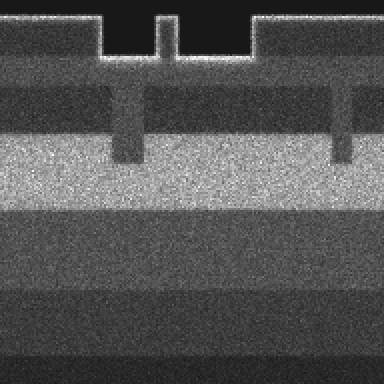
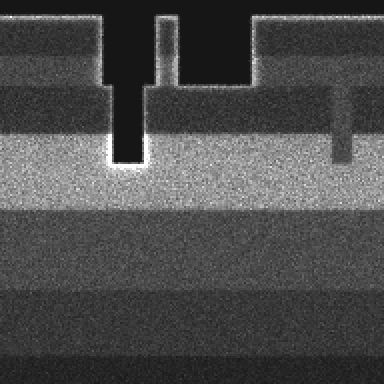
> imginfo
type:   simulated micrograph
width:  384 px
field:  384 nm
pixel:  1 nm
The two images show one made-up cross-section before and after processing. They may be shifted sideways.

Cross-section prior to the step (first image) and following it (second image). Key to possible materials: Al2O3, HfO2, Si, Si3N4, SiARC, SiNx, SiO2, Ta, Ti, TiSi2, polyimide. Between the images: SiO2 was removed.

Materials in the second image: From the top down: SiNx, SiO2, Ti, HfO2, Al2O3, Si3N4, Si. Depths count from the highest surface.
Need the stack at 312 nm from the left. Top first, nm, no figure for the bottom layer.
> SiNx 40, SiO2 30, Ti 48, HfO2 76, Al2O3 80, Si3N4 66, Si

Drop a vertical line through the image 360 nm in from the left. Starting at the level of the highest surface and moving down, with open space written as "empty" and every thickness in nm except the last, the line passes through SiNx 40, SiO2 30, Ti 48, HfO2 76, Al2O3 80, Si3N4 66, Si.